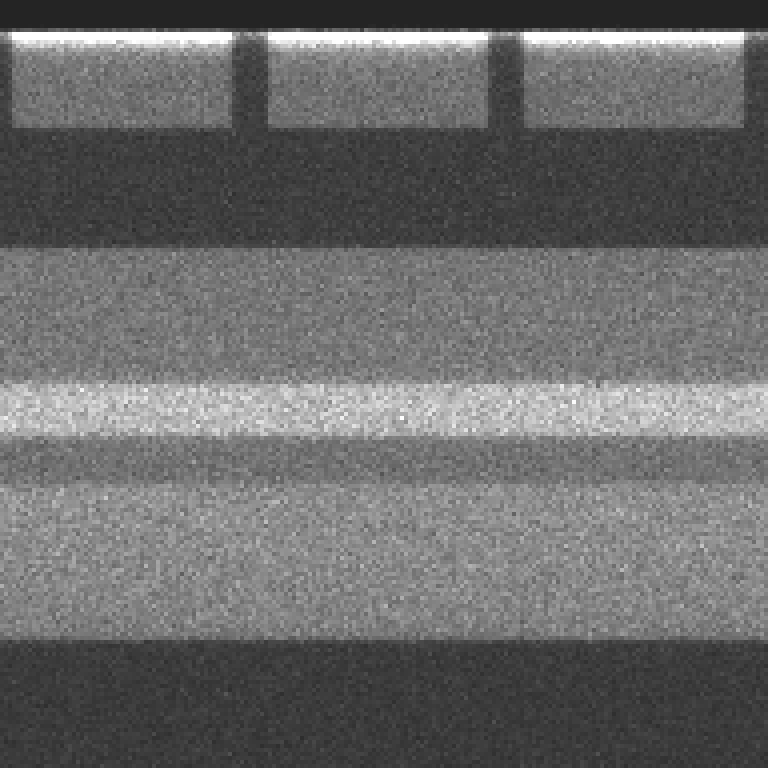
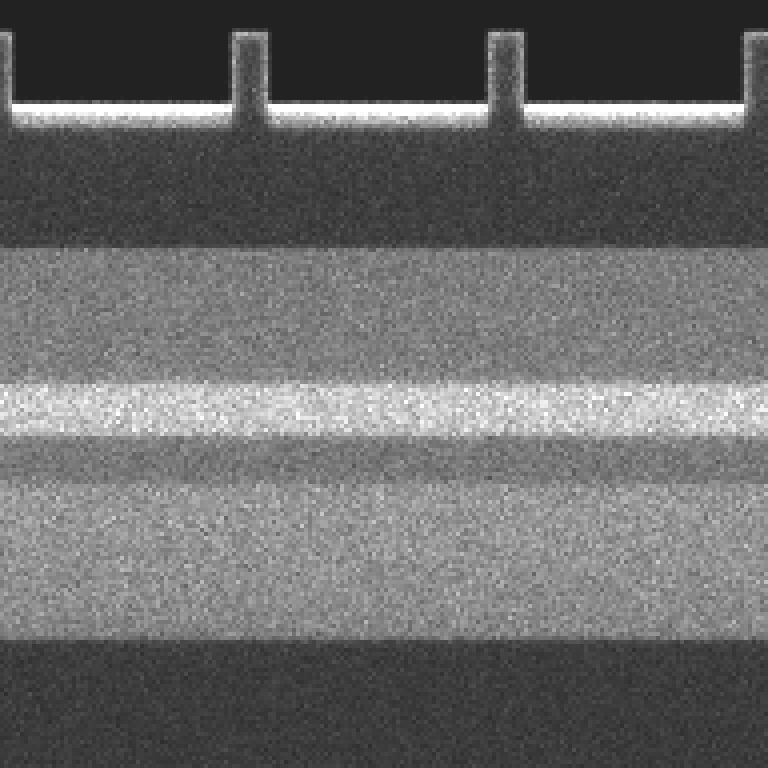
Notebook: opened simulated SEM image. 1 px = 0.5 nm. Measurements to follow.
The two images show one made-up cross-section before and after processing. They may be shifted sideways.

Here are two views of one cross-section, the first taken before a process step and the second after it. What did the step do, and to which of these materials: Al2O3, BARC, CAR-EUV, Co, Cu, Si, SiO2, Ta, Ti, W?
It removed SiO2.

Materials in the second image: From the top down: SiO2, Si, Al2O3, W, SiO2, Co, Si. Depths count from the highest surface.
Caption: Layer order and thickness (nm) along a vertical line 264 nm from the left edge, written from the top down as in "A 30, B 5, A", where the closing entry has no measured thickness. empty 36, SiO2 12, Si 60, Al2O3 68, W 26, SiO2 24, Co 78, Si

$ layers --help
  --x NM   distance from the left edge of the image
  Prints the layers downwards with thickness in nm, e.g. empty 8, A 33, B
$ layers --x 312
empty 36, SiO2 12, Si 60, Al2O3 68, W 26, SiO2 24, Co 78, Si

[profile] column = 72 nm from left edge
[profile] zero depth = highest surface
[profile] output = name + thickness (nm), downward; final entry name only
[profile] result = empty 36, SiO2 12, Si 60, Al2O3 68, W 26, SiO2 24, Co 78, Si